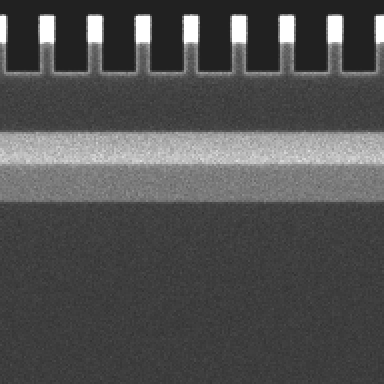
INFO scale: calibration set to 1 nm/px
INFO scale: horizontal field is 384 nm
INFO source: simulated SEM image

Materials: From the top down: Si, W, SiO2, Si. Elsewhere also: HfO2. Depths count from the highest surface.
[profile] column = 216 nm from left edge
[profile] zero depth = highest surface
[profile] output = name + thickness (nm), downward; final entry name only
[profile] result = empty 56, Si 60, W 32, SiO2 38, Si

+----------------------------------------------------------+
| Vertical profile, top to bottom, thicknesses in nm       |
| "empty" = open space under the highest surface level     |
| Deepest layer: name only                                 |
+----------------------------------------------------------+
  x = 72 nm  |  empty 56, Si 60, W 32, SiO2 38, Si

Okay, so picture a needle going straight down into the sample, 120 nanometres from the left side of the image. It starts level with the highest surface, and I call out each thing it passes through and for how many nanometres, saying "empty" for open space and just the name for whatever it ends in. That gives empty 56, Si 60, W 32, SiO2 38, Si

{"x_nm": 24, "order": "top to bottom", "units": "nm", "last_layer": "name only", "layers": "empty 56, Si 60, W 32, SiO2 38, Si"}